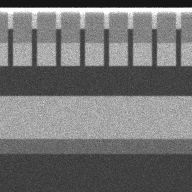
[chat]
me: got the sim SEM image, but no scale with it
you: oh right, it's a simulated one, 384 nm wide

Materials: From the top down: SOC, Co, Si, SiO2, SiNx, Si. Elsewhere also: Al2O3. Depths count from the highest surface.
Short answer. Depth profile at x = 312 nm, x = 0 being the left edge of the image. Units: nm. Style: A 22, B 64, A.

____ SOC 6, Co 36, Si 134, SiO2 86, SiNx 30, Si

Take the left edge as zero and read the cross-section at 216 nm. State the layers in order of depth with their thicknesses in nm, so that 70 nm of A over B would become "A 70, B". SOC 6, Co 36, Si 134, SiO2 86, SiNx 30, Si